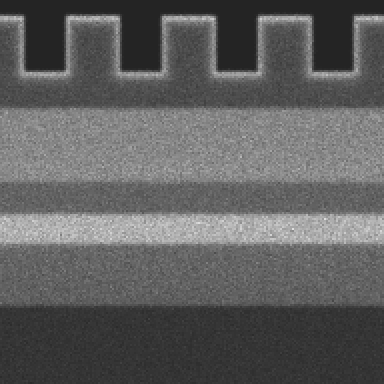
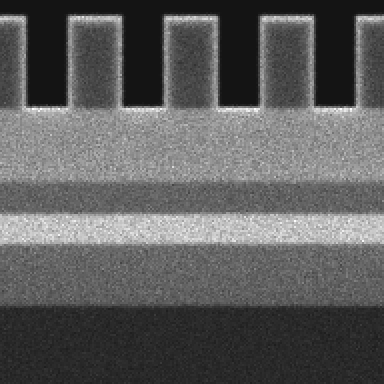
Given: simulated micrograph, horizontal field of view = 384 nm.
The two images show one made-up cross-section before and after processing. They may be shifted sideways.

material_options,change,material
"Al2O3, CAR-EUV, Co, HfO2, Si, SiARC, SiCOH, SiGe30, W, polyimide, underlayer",removed,underlayer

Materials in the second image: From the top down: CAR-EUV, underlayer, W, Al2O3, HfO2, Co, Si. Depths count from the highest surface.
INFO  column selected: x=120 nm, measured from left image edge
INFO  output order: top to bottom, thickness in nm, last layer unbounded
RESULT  CAR-EUV 56, underlayer 36, W 74, Al2O3 32, HfO2 30, Co 62, Si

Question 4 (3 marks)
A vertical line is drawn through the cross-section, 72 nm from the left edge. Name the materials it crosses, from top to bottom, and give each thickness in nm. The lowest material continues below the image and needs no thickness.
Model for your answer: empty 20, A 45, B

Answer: CAR-EUV 56, underlayer 36, W 74, Al2O3 32, HfO2 30, Co 62, Si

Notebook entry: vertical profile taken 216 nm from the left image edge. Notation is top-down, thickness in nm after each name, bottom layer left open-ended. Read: CAR-EUV 56, underlayer 36, W 74, Al2O3 32, HfO2 30, Co 62, Si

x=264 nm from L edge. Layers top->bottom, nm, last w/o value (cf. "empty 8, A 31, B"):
CAR-EUV 56, underlayer 36, W 74, Al2O3 32, HfO2 30, Co 62, Si